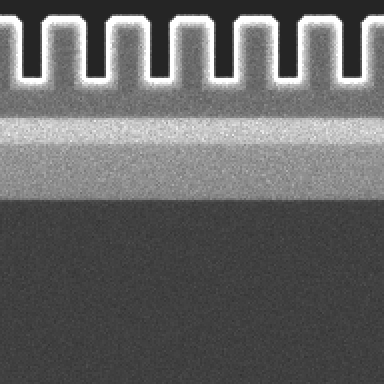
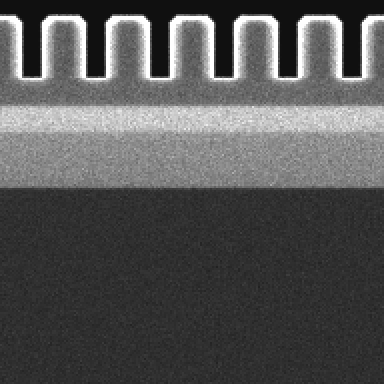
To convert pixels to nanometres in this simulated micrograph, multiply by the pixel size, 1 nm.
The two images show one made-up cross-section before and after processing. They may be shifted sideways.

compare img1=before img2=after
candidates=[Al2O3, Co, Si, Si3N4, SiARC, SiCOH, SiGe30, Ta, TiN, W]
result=removed:Al2O3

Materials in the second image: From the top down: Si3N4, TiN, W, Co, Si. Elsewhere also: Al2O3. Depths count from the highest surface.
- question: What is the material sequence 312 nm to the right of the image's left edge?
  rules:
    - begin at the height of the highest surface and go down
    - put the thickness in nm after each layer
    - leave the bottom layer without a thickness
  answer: Si3N4 62, TiN 28, W 26, Co 56, Si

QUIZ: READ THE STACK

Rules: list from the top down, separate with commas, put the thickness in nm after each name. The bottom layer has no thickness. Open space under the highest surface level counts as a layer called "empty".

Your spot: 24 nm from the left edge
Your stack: empty 62, TiN 28, W 26, Co 56, Si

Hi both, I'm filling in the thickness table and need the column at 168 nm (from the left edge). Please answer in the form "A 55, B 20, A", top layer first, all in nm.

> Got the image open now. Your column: empty 62, TiN 28, W 26, Co 56, Si